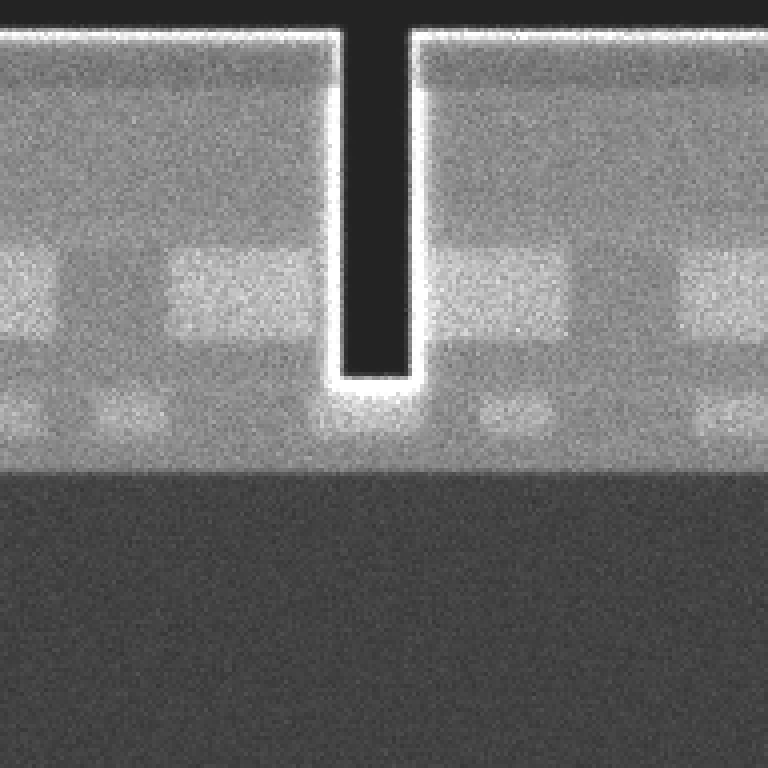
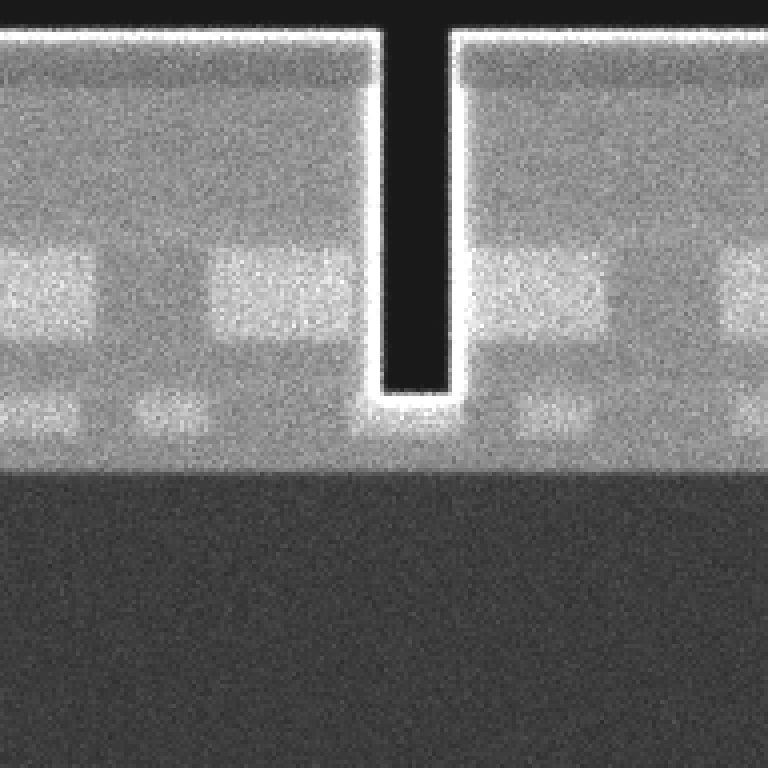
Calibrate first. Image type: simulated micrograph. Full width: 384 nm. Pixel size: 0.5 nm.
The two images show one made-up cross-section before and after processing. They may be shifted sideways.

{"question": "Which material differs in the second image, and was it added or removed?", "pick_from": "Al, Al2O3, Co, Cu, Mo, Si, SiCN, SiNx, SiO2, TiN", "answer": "Al2O3, removed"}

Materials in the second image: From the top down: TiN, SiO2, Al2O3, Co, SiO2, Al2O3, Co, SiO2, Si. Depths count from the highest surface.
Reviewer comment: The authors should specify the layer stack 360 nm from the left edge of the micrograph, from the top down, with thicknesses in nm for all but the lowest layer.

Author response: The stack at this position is TiN 28, SiO2 64, Al2O3 16, Co 46, SiO2 20, Al2O3 8, SiO2 38, Si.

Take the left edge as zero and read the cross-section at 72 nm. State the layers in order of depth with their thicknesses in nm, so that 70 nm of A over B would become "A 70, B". TiN 28, SiO2 64, Al2O3 16, SiO2 66, Al2O3 8, Co 20, SiO2 18, Si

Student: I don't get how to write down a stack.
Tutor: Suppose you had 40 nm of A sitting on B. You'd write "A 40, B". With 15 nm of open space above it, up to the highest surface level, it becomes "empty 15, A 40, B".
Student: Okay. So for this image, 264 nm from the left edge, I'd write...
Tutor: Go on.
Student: TiN 28, SiO2 64, Al2O3 16, Co 46, SiO2 20, Al2O3 8, Co 20, SiO2 18, Si